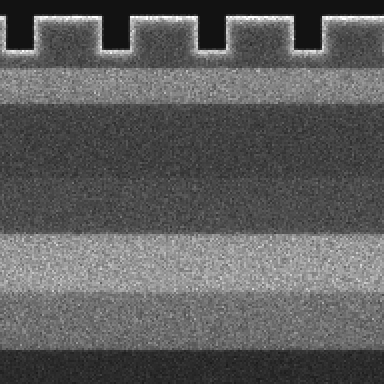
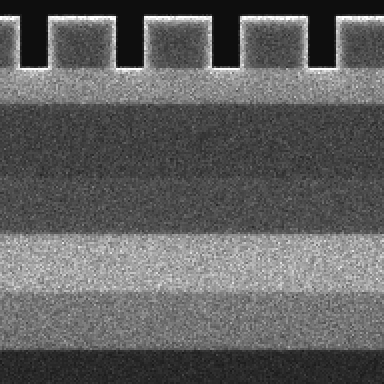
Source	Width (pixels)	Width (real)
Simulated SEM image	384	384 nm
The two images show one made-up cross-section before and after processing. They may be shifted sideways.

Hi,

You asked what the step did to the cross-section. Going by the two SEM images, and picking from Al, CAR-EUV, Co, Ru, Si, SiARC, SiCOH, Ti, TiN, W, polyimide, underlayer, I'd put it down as underlayer, removed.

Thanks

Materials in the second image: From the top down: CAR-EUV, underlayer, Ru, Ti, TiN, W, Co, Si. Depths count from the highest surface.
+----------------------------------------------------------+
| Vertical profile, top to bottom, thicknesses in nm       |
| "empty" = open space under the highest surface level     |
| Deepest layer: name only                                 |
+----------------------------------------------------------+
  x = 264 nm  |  CAR-EUV 34, underlayer 18, Ru 36, Ti 74, TiN 56, W 58, Co 58, Si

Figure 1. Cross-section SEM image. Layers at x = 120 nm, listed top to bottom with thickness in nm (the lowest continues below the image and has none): empty 52, Ru 36, Ti 74, TiN 56, W 58, Co 58, Si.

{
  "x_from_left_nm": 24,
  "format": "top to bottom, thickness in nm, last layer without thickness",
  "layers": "empty 52, Ru 36, Ti 74, TiN 56, W 58, Co 58, Si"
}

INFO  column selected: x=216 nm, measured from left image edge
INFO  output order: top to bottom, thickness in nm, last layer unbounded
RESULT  empty 52, Ru 36, Ti 74, TiN 56, W 58, Co 58, Si